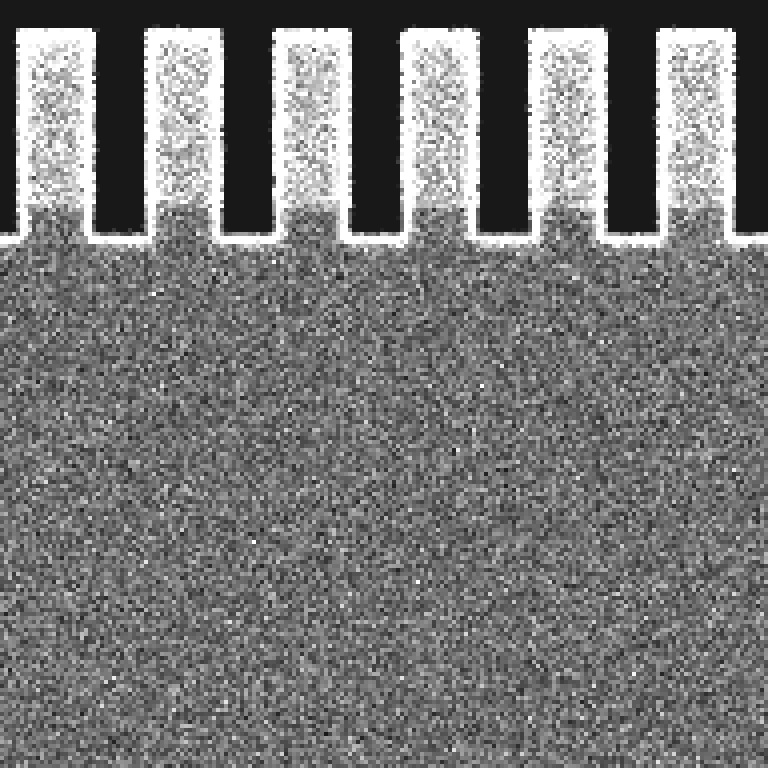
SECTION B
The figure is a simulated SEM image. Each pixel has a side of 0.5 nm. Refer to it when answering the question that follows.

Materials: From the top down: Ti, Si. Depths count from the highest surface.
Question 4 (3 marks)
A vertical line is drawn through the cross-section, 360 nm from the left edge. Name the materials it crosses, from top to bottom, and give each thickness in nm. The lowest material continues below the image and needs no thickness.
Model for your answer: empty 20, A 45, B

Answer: Ti 88, Si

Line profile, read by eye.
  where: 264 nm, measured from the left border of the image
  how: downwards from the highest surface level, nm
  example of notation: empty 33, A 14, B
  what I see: empty 102, Si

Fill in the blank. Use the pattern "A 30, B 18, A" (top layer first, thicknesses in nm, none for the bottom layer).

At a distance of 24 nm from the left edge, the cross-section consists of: Ti 88, Si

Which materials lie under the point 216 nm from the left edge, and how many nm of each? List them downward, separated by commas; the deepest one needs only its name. Ti 88, Si